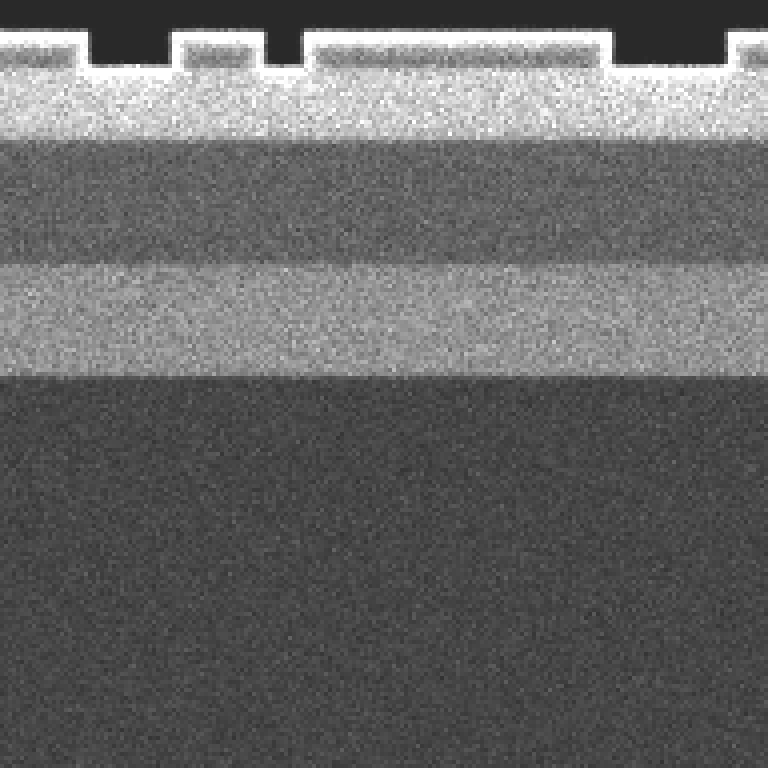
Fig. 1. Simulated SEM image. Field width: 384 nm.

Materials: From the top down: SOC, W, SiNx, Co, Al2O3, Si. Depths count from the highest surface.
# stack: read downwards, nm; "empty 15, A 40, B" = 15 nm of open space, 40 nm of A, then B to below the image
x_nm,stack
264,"SOC 18, W 36, SiNx 62, Co 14, Al2O3 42, Si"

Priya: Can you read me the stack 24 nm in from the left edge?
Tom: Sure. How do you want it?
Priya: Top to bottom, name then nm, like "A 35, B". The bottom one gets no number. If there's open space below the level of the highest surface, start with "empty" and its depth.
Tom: SOC 18, W 36, SiNx 62, Co 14, Al2O3 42, Si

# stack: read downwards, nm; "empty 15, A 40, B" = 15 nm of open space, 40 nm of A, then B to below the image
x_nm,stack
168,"SOC 18, W 36, SiNx 62, Co 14, Al2O3 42, Si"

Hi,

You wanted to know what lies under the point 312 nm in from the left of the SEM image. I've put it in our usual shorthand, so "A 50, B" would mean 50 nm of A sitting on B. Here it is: empty 18, W 36, SiNx 62, Co 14, Al2O3 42, Si